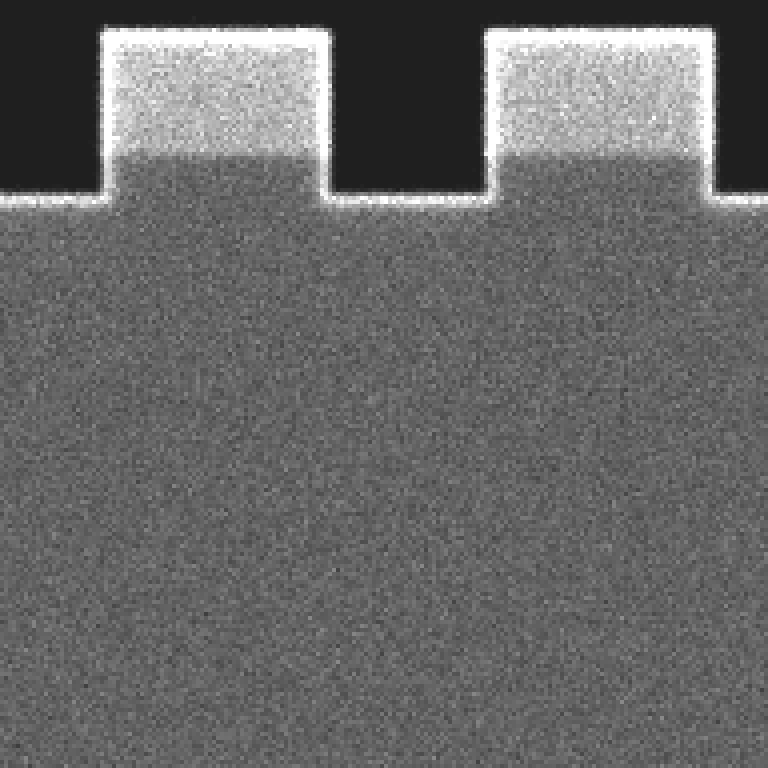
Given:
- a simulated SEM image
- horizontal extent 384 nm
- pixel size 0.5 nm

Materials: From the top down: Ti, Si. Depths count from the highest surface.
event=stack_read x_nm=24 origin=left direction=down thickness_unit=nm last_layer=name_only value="empty 82, Si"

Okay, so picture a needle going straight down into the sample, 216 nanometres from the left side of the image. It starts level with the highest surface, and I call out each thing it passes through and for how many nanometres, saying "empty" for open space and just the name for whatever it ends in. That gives empty 82, Si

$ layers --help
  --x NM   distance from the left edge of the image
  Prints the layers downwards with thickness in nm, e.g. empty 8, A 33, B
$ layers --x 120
Ti 62, Si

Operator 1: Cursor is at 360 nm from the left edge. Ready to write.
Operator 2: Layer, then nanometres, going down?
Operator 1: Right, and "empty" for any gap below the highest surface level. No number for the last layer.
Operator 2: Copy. empty 82, Si